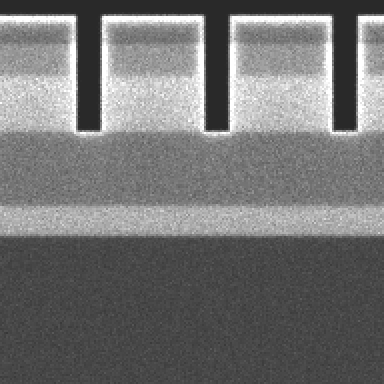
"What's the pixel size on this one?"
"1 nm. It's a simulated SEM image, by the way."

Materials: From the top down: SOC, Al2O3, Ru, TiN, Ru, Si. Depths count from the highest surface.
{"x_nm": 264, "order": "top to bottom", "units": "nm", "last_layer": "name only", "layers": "SOC 28, Al2O3 32, Ru 56, TiN 74, Ru 30, Si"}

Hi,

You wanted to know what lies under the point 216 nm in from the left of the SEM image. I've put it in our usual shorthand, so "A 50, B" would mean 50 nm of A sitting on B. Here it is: empty 116, TiN 74, Ru 30, Si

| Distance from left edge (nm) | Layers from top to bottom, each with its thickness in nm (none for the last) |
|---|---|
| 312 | SOC 28, Al2O3 32, Ru 56, TiN 74, Ru 30, Si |